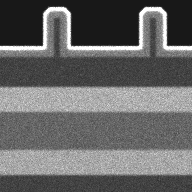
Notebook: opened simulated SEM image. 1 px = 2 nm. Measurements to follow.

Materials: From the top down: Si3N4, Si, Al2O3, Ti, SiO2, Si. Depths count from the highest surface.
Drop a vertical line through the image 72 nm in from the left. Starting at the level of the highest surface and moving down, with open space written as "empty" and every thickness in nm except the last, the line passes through empty 78, Si3N4 20, Si 60, Al2O3 50, Ti 76, SiO2 50, Si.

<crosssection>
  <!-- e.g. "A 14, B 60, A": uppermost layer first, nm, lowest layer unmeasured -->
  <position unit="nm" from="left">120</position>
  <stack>Si3N4 98, Si 60, Al2O3 50, Ti 76, SiO2 50, Si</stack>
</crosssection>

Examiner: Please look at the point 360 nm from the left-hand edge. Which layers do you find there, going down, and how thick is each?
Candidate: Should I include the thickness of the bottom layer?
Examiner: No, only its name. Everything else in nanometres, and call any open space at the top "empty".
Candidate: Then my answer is empty 78, Si3N4 20, Si 60, Al2O3 50, Ti 76, SiO2 50, Si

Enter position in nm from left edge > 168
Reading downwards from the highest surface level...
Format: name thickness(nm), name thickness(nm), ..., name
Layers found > empty 78, Si3N4 20, Si 60, Al2O3 50, Ti 76, SiO2 50, Si